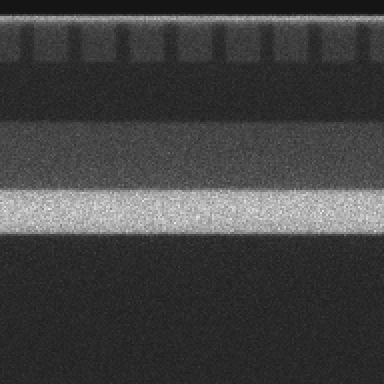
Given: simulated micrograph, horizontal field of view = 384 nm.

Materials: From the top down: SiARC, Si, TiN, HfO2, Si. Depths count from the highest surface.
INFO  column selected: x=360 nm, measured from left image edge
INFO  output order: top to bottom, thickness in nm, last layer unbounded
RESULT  SiARC 6, Si 100, TiN 68, HfO2 44, Si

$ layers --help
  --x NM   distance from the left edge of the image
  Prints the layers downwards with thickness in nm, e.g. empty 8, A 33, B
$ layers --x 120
SiARC 6, Si 100, TiN 68, HfO2 44, Si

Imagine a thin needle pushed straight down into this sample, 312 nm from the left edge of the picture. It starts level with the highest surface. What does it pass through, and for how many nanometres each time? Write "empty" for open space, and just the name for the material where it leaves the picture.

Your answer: SiARC 6, Si 100, TiN 68, HfO2 44, Si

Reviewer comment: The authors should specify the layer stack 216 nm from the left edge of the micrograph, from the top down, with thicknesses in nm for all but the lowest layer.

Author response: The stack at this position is SiARC 6, Si 100, TiN 68, HfO2 44, Si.